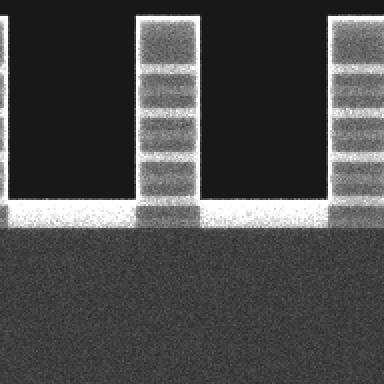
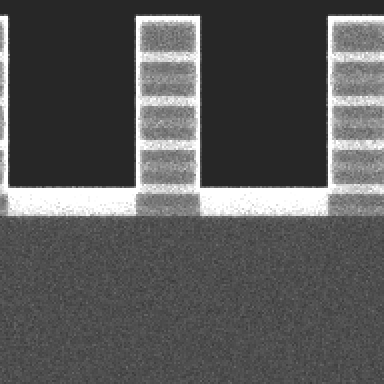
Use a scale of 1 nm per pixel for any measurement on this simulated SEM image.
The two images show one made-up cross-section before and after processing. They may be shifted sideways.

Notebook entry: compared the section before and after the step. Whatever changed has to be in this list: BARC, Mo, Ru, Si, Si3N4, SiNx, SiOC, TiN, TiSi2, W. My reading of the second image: Si3N4 removed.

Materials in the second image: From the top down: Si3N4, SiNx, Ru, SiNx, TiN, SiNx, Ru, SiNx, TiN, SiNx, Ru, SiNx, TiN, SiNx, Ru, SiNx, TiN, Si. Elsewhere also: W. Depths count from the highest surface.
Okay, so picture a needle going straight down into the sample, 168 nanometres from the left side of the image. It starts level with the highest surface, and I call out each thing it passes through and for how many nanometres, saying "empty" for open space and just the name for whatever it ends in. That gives Si3N4 10, SiNx 26, Ru 10, SiNx 12, TiN 10, SiNx 12, Ru 10, SiNx 12, TiN 10, SiNx 12, Ru 10, SiNx 12, TiN 10, SiNx 12, Ru 10, SiNx 12, TiN 10, Si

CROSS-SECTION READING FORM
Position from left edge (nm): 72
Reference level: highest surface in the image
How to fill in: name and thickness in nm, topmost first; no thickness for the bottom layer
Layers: empty 172, W 28, Si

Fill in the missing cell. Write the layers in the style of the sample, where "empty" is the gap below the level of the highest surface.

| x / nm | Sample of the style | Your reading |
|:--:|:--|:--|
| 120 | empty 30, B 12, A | empty 172, W 28, Si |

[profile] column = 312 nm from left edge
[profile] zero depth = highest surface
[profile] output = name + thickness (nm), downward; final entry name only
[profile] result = empty 172, W 28, Si